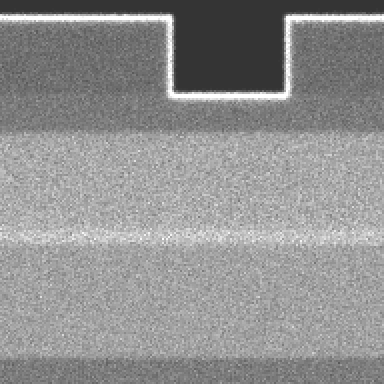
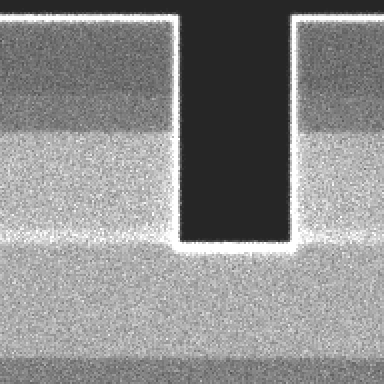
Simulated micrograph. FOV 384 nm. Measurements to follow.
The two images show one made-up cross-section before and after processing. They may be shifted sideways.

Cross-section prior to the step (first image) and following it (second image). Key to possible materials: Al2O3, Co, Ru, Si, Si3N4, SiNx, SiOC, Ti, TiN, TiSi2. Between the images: Co and Ru and Si3N4 was removed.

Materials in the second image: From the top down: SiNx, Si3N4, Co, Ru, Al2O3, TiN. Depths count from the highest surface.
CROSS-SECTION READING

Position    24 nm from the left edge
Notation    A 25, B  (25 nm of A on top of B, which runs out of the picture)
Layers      SiNx 78, Si3N4 38, Co 98, Ru 14, Al2O3 114, TiN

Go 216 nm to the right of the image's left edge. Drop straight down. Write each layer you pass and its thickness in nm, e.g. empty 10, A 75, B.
empty 228, Al2O3 114, TiN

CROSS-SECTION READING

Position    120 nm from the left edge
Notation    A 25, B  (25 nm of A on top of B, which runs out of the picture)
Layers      SiNx 78, Si3N4 38, Co 98, Ru 14, Al2O3 114, TiN